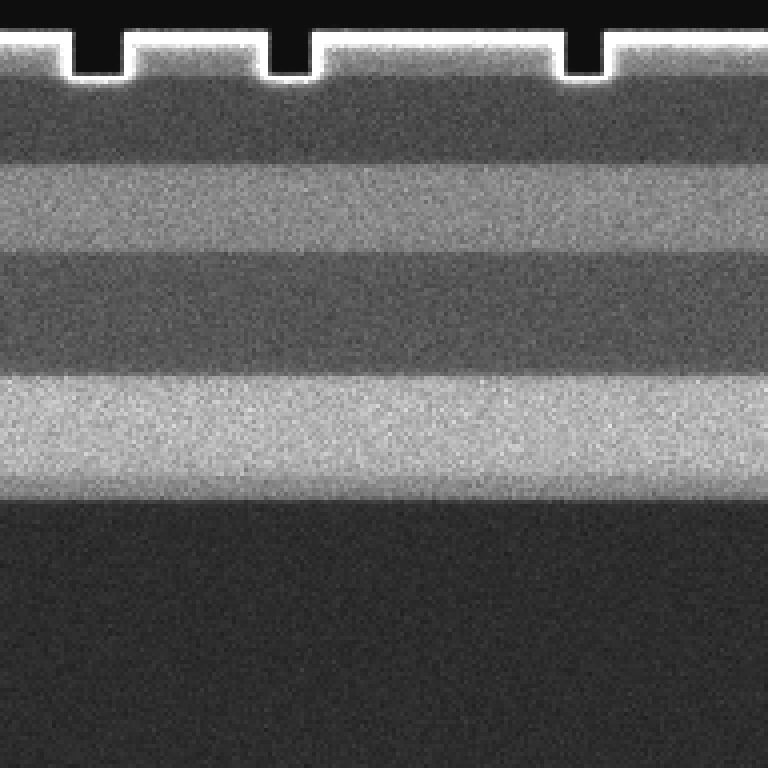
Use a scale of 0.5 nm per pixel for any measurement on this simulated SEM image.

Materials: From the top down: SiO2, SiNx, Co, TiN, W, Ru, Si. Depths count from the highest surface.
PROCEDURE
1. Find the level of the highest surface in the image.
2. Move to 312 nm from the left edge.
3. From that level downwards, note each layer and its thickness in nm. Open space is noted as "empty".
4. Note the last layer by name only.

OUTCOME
SiO2 22, SiNx 44, Co 44, TiN 62, W 50, Ru 12, Si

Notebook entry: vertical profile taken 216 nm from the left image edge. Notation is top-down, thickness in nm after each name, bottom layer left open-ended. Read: SiO2 22, SiNx 44, Co 44, TiN 62, W 50, Ru 12, Si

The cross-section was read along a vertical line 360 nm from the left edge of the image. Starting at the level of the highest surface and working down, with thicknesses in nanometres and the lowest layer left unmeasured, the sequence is SiO2 22, SiNx 44, Co 44, TiN 62, W 50, Ru 12, Si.